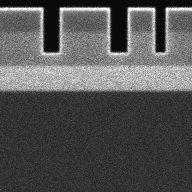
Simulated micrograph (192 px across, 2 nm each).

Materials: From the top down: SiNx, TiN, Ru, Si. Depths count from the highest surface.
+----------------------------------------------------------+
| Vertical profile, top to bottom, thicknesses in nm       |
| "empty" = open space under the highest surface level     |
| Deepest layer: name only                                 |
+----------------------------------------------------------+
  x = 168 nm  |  SiNx 48, TiN 68, Ru 50, Si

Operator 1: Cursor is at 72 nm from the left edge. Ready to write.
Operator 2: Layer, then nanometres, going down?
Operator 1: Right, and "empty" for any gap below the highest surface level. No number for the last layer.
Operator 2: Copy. SiNx 48, TiN 68, Ru 50, Si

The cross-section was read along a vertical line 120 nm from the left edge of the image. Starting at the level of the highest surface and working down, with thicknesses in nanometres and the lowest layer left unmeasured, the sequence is SiNx 48, TiN 68, Ru 50, Si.